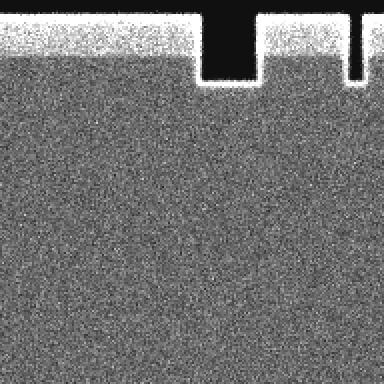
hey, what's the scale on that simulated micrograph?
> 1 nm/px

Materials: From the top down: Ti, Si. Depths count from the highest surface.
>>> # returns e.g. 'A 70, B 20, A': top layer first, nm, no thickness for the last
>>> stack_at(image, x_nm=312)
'Ti 40, Si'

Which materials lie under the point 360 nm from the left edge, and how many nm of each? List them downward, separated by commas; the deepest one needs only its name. empty 66, Si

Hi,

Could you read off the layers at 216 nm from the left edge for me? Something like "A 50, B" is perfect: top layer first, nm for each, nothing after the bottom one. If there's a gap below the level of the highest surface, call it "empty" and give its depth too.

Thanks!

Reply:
empty 66, Si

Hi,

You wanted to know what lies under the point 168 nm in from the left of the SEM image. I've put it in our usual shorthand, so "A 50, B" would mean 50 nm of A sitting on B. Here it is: Ti 40, Si